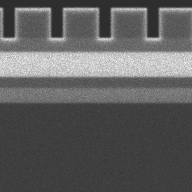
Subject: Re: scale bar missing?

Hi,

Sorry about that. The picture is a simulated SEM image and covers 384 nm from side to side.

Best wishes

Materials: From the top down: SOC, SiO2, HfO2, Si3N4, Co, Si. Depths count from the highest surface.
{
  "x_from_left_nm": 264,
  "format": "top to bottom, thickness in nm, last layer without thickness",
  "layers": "SOC 60, SiO2 28, HfO2 50, Si3N4 22, Co 30, Si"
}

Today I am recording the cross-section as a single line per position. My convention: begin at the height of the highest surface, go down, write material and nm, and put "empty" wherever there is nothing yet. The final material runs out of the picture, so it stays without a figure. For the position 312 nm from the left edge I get empty 60, SiO2 28, HfO2 50, Si3N4 22, Co 30, Si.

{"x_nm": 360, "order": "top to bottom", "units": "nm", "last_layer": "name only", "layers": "SOC 60, SiO2 28, HfO2 50, Si3N4 22, Co 30, Si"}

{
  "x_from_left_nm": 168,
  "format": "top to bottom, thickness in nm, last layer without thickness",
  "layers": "SOC 60, SiO2 28, HfO2 50, Si3N4 22, Co 30, Si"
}